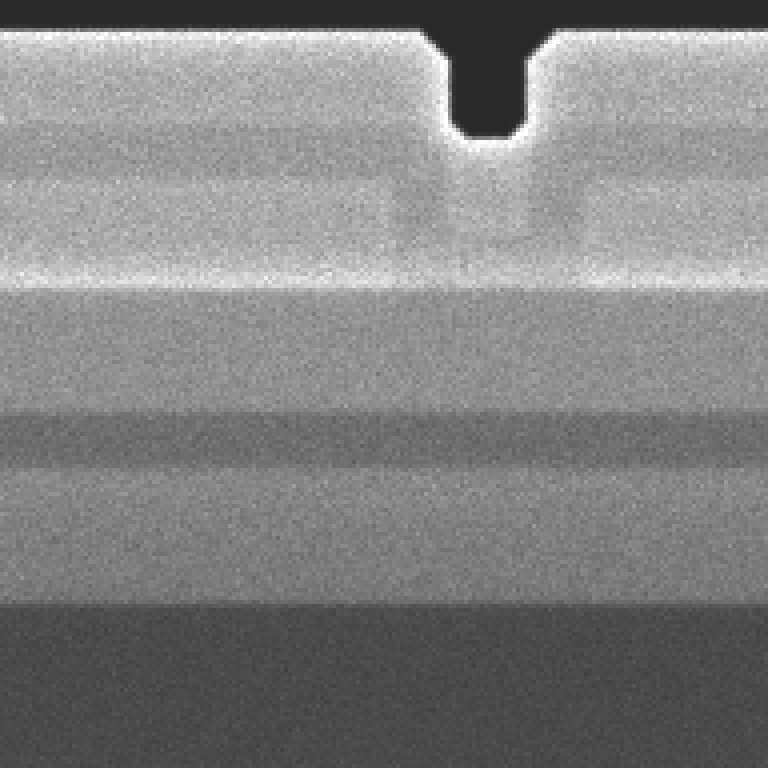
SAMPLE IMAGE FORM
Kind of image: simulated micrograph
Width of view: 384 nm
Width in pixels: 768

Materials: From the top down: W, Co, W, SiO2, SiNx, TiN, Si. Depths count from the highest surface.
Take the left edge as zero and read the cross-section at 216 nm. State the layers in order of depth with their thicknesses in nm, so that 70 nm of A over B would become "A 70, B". empty 8, W 46, Co 74, SiO2 62, SiNx 28, TiN 68, Si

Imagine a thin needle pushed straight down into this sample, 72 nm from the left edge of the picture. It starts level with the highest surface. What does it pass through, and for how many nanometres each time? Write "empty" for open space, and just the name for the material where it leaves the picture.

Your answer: W 46, Co 28, W 54, SiO2 62, SiNx 28, TiN 68, Si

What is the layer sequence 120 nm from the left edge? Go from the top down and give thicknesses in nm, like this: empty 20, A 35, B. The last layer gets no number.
W 46, Co 28, W 54, SiO2 62, SiNx 28, TiN 68, Si